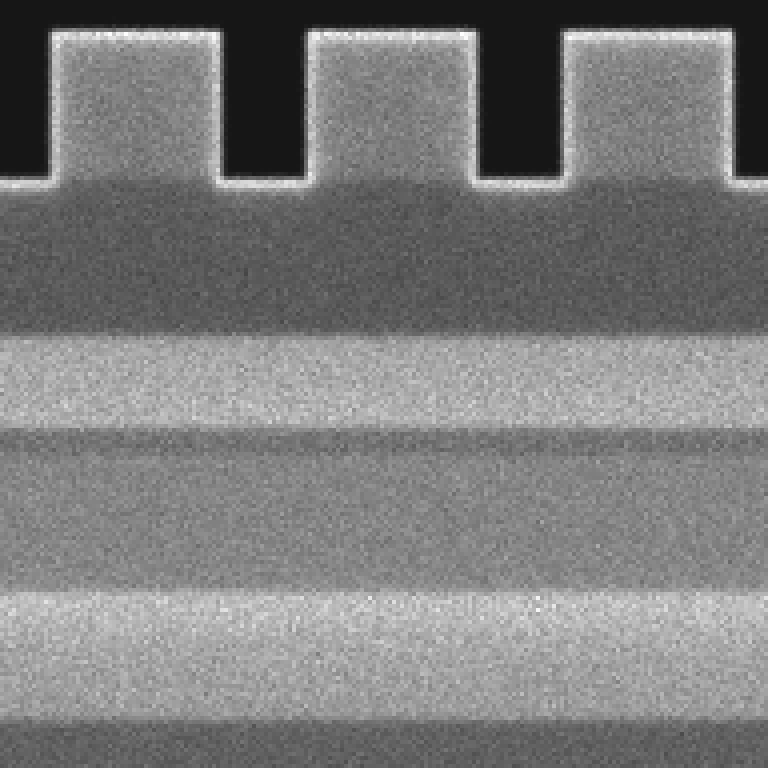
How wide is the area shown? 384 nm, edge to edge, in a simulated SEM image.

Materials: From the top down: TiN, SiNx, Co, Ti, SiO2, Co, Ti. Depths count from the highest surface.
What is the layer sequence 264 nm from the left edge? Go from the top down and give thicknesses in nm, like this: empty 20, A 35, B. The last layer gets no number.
empty 74, SiNx 78, Co 46, Ti 14, SiO2 68, Co 64, Ti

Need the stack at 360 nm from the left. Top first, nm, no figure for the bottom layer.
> TiN 74, SiNx 78, Co 46, Ti 14, SiO2 68, Co 64, Ti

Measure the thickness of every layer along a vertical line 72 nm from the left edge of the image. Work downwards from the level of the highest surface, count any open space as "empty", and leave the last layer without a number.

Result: TiN 74, SiNx 78, Co 46, Ti 14, SiO2 68, Co 64, Ti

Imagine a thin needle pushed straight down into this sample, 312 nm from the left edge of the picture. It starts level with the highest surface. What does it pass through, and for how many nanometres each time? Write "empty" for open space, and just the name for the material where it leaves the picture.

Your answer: TiN 74, SiNx 78, Co 46, Ti 14, SiO2 68, Co 64, Ti